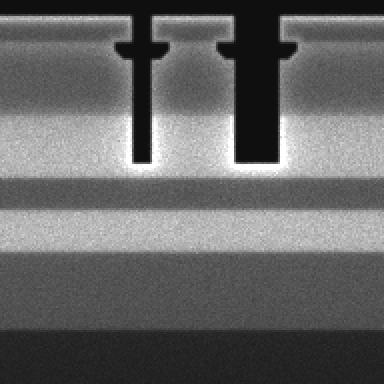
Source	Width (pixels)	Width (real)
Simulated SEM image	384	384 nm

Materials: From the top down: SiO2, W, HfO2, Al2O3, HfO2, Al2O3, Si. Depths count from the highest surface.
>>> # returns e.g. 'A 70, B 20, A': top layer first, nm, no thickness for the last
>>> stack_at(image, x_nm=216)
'SiO2 26, empty 10, W 64, HfO2 62, Al2O3 32, HfO2 42, Al2O3 78, Si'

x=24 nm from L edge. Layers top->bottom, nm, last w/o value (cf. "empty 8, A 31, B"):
SiO2 26, W 74, HfO2 62, Al2O3 32, HfO2 42, Al2O3 78, Si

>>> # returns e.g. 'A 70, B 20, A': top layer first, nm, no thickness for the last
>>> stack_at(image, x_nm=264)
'empty 148, HfO2 14, Al2O3 32, HfO2 42, Al2O3 78, Si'